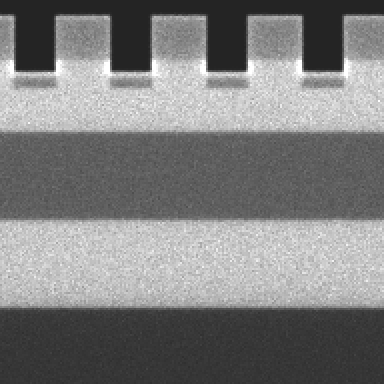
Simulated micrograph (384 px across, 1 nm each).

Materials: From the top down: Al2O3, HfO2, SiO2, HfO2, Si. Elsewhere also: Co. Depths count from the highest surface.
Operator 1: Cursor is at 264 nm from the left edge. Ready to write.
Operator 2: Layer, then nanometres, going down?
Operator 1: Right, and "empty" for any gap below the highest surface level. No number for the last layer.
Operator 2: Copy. Co 44, HfO2 72, SiO2 88, HfO2 88, Si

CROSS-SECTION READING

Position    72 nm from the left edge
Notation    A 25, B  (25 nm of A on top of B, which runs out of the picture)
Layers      Co 44, HfO2 72, SiO2 88, HfO2 88, Si